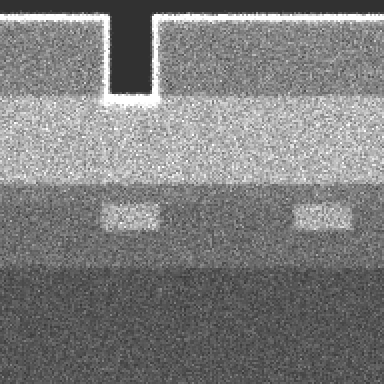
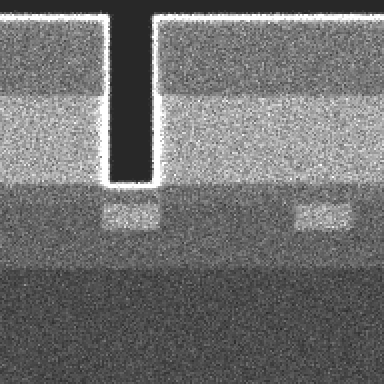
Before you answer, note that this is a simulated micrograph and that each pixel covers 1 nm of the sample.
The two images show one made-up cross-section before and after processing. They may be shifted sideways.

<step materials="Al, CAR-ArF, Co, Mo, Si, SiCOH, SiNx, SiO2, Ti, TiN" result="removed SiO2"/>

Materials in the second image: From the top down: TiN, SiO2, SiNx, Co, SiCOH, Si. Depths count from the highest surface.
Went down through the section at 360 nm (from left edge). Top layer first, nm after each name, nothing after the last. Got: TiN 80, SiO2 88, SiNx 20, SiCOH 64, Si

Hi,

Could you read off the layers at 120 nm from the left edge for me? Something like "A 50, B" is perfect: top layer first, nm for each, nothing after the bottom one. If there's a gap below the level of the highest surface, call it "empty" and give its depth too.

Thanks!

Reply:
empty 168, SiNx 20, Co 26, SiCOH 38, Si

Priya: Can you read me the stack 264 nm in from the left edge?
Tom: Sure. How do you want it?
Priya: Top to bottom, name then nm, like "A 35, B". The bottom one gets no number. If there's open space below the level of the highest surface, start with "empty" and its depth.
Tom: TiN 80, SiO2 88, SiNx 20, SiCOH 64, Si